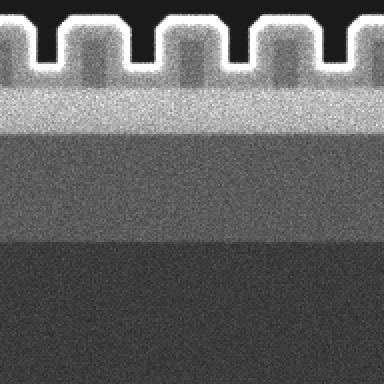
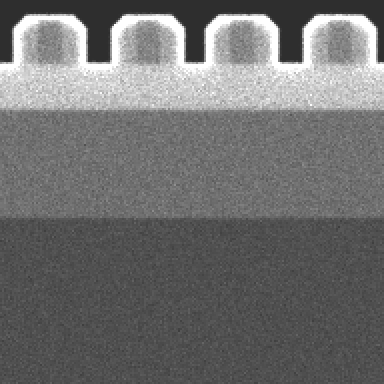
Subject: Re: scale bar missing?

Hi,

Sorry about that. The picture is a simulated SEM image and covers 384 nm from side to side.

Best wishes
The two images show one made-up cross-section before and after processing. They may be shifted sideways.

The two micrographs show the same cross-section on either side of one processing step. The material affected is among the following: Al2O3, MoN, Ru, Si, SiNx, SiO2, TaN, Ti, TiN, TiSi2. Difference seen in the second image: SiO2 removed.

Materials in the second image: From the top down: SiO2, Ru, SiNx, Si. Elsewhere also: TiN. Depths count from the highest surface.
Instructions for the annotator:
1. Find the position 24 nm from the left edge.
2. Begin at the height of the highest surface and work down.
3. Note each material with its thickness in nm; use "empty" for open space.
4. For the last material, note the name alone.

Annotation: empty 2, SiO2 46, Ru 46, SiNx 108, Si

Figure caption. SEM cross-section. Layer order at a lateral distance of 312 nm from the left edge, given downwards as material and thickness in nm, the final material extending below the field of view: empty 4, SiO2 44, Ru 46, SiNx 108, Si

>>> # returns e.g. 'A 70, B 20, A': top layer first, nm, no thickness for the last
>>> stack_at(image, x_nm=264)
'SiO2 48, Ru 46, SiNx 108, Si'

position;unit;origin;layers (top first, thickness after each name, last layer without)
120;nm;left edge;empty 4, SiO2 44, Ru 46, SiNx 108, Si